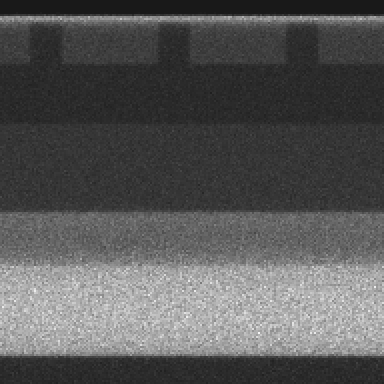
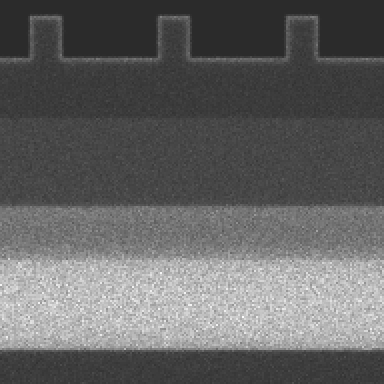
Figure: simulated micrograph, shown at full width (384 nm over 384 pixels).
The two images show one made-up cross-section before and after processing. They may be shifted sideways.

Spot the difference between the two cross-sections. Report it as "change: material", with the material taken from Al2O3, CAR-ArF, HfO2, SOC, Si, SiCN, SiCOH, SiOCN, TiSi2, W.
removed: SOC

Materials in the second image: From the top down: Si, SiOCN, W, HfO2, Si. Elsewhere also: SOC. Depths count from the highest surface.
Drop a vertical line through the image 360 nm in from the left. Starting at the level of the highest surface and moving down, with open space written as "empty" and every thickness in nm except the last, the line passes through empty 42, Si 60, SiOCN 88, W 54, HfO2 90, Si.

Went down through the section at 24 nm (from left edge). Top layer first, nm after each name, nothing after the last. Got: empty 42, Si 60, SiOCN 88, W 54, HfO2 90, Si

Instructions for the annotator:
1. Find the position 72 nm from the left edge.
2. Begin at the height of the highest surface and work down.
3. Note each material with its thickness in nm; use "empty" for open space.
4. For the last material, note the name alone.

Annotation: empty 42, Si 60, SiOCN 88, W 54, HfO2 90, Si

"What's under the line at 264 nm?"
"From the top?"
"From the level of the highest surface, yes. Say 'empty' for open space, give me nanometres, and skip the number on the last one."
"empty 42, Si 60, SiOCN 88, W 54, HfO2 90, Si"